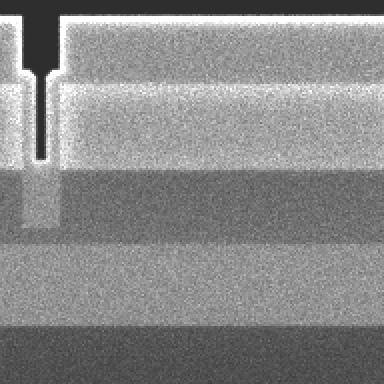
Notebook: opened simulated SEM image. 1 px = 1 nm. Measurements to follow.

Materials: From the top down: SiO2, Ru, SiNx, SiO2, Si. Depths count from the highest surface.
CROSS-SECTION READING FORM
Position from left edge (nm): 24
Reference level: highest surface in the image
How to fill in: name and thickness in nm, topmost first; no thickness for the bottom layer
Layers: empty 54, SiO2 158, SiNx 16, SiO2 82, Si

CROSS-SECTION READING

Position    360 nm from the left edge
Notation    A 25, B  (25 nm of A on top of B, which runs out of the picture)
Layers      SiO2 68, Ru 86, SiNx 74, SiO2 82, Si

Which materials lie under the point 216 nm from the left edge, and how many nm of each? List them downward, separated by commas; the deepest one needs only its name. SiO2 68, Ru 86, SiNx 74, SiO2 82, Si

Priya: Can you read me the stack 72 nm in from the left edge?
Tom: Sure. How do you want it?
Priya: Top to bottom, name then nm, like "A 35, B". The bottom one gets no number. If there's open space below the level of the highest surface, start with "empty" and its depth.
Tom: SiO2 68, Ru 86, SiNx 74, SiO2 82, Si